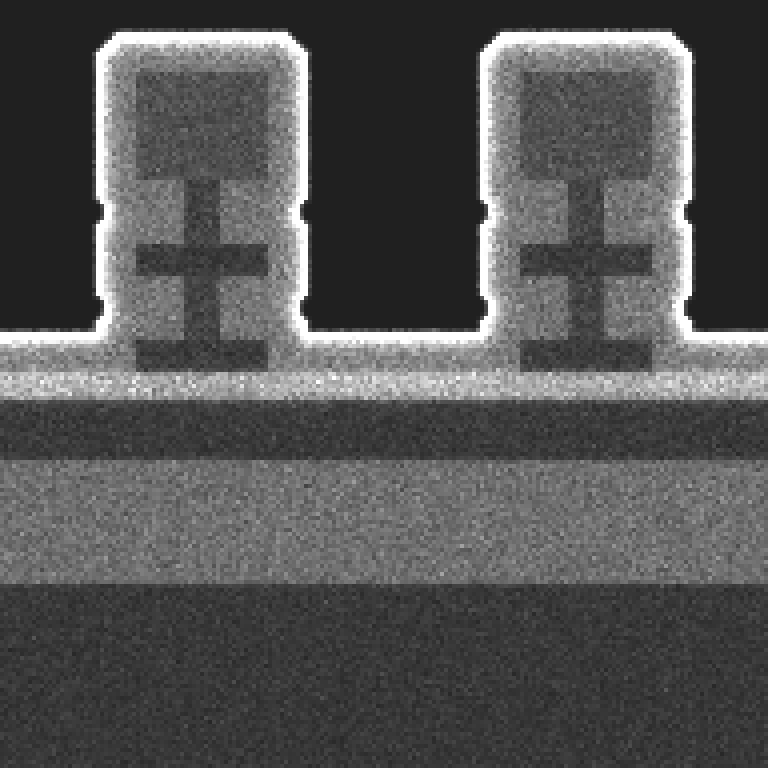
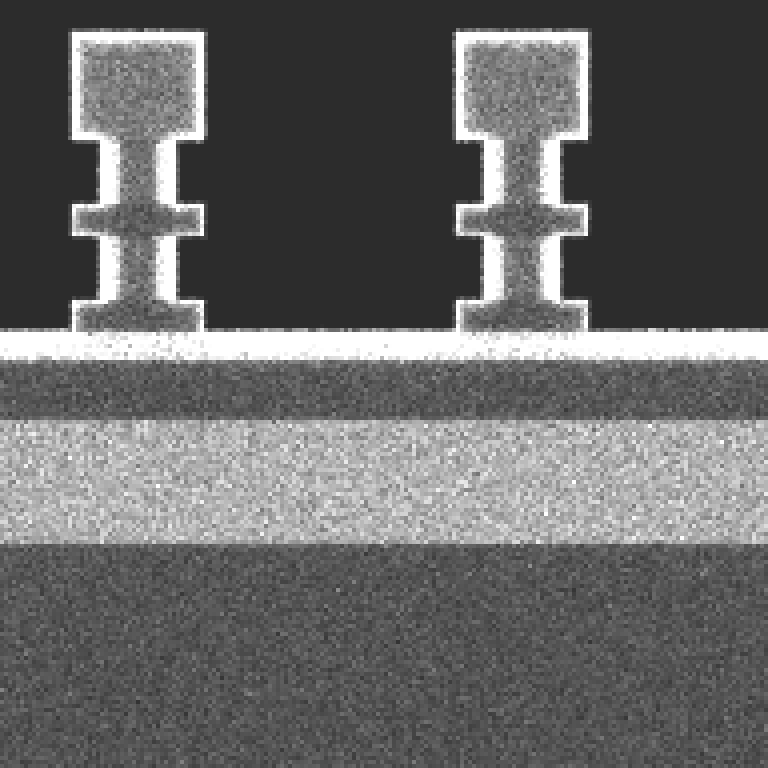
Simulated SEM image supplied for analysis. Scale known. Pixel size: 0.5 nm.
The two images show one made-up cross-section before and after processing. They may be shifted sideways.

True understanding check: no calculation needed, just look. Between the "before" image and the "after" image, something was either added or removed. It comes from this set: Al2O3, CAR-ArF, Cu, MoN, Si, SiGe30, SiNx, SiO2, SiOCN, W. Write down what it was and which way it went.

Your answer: Al2O3 (removed)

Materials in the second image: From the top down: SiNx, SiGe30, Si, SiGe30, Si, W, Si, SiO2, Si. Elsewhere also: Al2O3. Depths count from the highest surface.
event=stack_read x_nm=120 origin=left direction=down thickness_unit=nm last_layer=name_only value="empty 150, W 14, Si 30, SiO2 62, Si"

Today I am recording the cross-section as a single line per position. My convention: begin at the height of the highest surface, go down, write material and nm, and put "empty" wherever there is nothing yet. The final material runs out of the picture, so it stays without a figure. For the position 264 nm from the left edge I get SiNx 54, SiGe30 32, Si 16, SiGe30 32, Si 16, W 14, Si 30, SiO2 62, Si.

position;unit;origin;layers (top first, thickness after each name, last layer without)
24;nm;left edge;empty 150, W 14, Si 30, SiO2 62, Si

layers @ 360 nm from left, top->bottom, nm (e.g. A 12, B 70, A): empty 150, W 14, Si 30, SiO2 62, Si